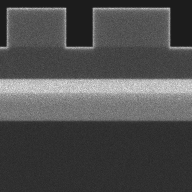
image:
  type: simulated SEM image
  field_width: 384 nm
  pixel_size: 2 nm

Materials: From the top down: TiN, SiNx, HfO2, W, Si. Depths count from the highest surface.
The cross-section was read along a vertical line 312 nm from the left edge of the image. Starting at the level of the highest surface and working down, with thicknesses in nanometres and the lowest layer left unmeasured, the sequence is TiN 78, SiNx 64, HfO2 28, W 56, Si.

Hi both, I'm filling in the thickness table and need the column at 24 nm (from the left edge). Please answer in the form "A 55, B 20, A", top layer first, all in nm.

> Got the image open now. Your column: TiN 78, SiNx 64, HfO2 28, W 56, Si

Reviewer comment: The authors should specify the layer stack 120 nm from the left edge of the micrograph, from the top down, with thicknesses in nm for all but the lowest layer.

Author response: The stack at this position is TiN 78, SiNx 64, HfO2 28, W 56, Si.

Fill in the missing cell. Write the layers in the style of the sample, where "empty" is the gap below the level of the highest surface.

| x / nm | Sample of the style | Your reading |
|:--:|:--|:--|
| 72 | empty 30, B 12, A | TiN 78, SiNx 64, HfO2 28, W 56, Si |